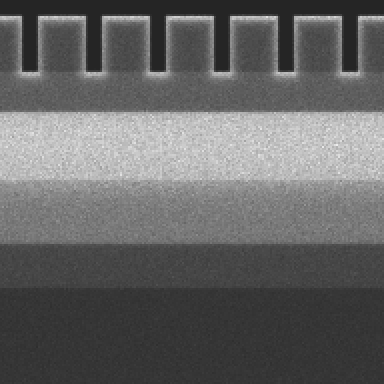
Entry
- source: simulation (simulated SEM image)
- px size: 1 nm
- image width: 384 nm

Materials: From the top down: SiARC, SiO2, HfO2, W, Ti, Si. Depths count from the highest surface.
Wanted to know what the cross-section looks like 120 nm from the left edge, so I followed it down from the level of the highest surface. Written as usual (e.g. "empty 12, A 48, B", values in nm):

SiARC 56, SiO2 40, HfO2 68, W 64, Ti 44, Si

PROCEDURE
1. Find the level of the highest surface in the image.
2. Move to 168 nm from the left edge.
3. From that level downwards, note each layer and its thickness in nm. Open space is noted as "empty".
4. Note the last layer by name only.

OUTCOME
SiARC 56, SiO2 40, HfO2 68, W 64, Ti 44, Si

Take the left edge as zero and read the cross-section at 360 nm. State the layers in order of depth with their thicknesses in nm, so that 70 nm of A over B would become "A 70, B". SiARC 56, SiO2 40, HfO2 68, W 64, Ti 44, Si